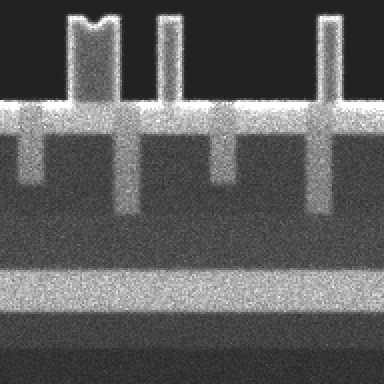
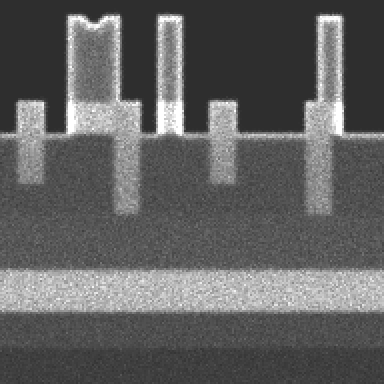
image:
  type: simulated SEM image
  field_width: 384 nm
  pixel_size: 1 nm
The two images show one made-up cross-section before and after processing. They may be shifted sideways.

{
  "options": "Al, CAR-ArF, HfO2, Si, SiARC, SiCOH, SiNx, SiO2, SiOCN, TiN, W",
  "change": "removed",
  "material": "HfO2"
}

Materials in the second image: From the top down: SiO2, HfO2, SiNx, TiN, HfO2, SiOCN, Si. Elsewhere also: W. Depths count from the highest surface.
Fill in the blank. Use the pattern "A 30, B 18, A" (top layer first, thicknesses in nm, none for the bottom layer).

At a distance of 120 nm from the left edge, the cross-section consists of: empty 86, W 112, TiN 56, HfO2 42, SiOCN 36, Si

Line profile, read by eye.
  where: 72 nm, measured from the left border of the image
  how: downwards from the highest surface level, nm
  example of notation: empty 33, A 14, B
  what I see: SiO2 86, HfO2 32, SiNx 80, TiN 56, HfO2 42, SiOCN 36, Si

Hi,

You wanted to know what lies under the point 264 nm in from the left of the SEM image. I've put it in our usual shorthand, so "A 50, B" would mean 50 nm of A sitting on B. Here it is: empty 118, SiNx 80, TiN 56, HfO2 42, SiOCN 36, Si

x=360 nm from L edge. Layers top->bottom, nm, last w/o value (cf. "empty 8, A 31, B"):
empty 118, SiNx 80, TiN 56, HfO2 42, SiOCN 36, Si